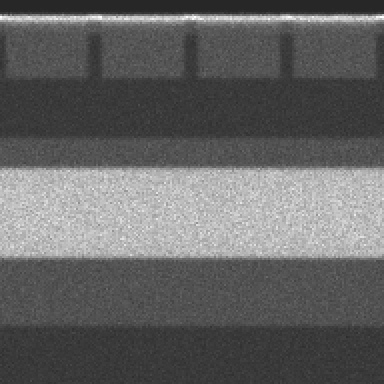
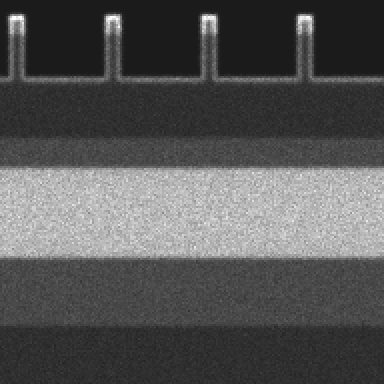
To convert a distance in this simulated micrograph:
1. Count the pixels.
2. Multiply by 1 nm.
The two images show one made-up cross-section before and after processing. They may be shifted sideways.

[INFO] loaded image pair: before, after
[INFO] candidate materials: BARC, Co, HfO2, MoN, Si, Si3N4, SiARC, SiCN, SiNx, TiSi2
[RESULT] removed SiARC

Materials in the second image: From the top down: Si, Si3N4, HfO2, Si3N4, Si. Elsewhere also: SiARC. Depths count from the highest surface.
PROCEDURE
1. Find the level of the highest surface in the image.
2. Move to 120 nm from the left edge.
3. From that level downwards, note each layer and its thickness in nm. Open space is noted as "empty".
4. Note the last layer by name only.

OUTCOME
empty 62, Si 60, Si3N4 30, HfO2 90, Si3N4 68, Si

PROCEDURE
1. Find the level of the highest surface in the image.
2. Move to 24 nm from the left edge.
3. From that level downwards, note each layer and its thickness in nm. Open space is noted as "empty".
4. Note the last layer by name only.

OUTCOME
empty 62, Si 60, Si3N4 30, HfO2 90, Si3N4 68, Si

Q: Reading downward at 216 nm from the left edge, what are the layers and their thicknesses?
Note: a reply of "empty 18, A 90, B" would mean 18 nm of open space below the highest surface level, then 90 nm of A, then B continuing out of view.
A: empty 62, Si 60, Si3N4 30, HfO2 90, Si3N4 68, Si